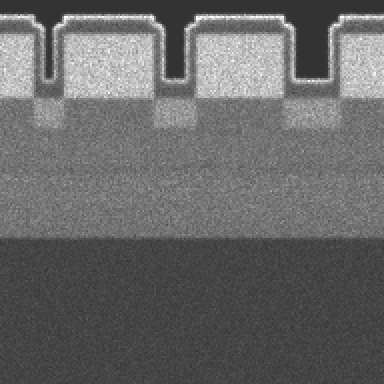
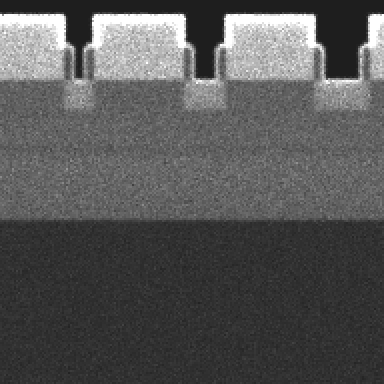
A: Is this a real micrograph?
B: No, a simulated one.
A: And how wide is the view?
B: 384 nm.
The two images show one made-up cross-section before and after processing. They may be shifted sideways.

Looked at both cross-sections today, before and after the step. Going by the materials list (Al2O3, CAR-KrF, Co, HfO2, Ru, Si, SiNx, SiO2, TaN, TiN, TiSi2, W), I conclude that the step removed TiN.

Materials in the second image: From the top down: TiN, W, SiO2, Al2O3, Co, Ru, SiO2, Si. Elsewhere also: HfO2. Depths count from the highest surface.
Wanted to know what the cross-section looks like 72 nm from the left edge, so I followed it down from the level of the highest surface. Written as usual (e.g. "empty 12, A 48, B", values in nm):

empty 32, TiN 32, W 30, SiO2 10, Al2O3 26, Co 10, Ru 50, SiO2 14, Si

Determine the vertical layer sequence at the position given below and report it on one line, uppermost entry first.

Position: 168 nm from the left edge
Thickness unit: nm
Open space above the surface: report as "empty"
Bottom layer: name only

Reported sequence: HfO2 64, SiO2 40, Al2O3 26, Co 10, Ru 50, SiO2 14, Si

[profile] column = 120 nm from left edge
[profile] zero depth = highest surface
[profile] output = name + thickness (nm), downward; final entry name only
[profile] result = HfO2 64, SiO2 40, Al2O3 26, Co 10, Ru 50, SiO2 14, Si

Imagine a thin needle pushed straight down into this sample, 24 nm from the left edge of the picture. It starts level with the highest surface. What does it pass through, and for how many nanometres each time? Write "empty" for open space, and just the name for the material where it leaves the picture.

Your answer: HfO2 64, SiO2 40, Al2O3 26, Co 10, Ru 50, SiO2 14, Si